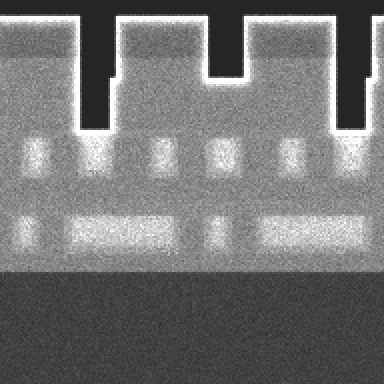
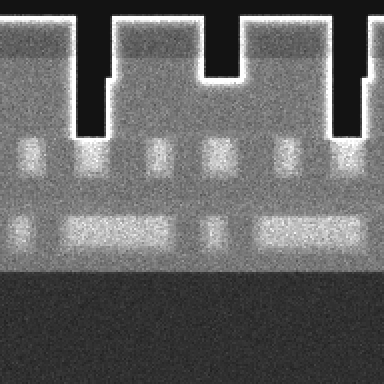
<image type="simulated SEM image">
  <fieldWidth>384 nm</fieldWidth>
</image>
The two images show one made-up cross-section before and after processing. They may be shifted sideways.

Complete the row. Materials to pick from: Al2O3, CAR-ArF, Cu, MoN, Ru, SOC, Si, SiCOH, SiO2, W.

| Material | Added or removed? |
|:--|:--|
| Al2O3 | removed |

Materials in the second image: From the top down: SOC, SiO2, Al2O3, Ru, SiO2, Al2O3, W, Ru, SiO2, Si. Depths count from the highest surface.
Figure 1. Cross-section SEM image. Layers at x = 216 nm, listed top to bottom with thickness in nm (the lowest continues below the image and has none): empty 62, SiO2 52, Al2O3 8, W 32, Ru 8, SiO2 22, Al2O3 16, W 30, Ru 8, SiO2 18, Si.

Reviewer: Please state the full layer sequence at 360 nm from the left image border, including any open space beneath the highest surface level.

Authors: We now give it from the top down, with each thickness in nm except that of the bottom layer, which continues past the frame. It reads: empty 122, Ru 40, SiO2 22, Al2O3 16, Ru 38, SiO2 18, Si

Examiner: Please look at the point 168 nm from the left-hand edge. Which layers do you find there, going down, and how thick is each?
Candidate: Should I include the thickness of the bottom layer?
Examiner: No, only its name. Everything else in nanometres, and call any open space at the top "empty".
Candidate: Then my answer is SOC 42, SiO2 72, Al2O3 8, Ru 40, SiO2 22, Al2O3 16, Ru 38, SiO2 18, Si